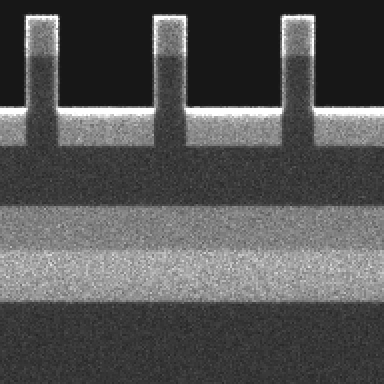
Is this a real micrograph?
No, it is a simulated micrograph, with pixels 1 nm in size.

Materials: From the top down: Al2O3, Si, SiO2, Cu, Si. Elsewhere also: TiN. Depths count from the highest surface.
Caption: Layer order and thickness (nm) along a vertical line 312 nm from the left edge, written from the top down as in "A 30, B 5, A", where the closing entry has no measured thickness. TiN 40, Si 150, SiO2 44, Cu 52, Si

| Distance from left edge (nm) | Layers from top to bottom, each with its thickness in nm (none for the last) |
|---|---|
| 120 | empty 92, Al2O3 38, Si 60, SiO2 44, Cu 52, Si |